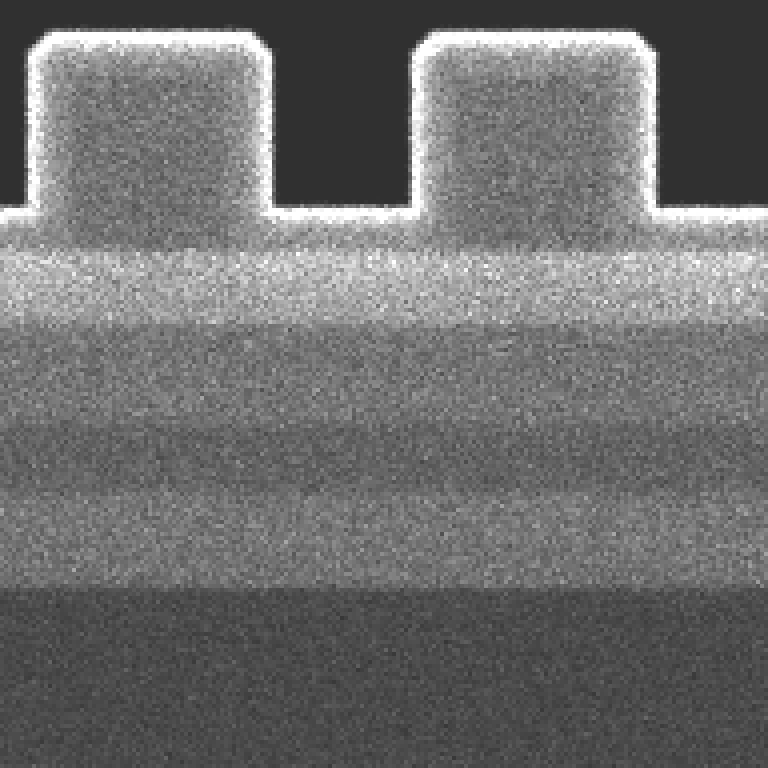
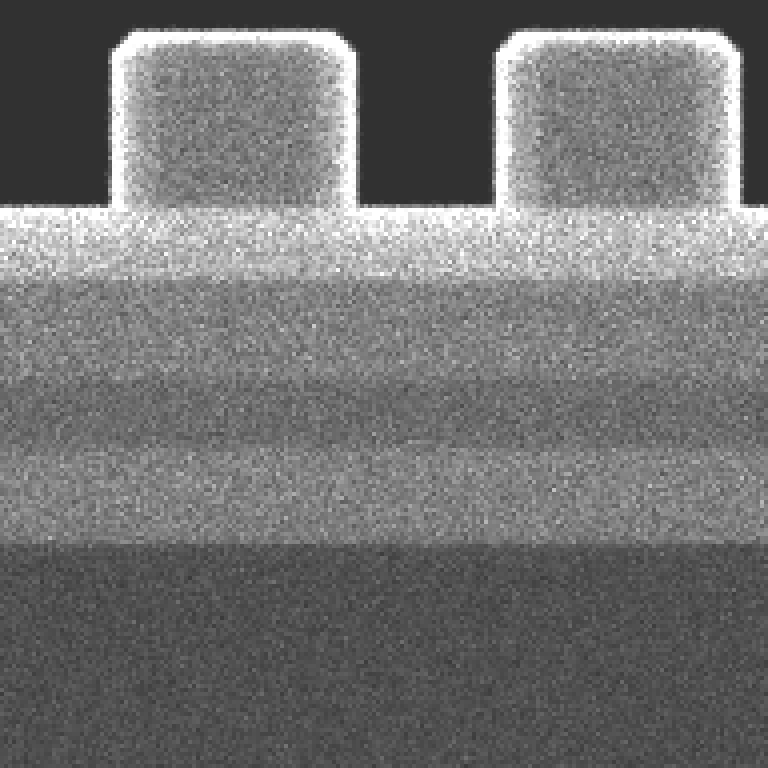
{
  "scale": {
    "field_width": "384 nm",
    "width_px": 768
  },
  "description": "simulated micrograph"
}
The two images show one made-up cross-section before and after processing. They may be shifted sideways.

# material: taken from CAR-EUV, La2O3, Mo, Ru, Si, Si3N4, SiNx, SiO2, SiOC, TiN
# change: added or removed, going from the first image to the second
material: SiO2
change: removed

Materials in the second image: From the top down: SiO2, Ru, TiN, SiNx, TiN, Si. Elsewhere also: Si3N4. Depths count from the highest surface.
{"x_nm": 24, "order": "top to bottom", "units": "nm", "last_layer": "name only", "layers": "empty 88, Ru 36, TiN 50, SiNx 34, TiN 48, Si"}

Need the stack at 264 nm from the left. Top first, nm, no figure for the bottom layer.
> SiO2 88, Ru 36, TiN 50, SiNx 34, TiN 48, Si